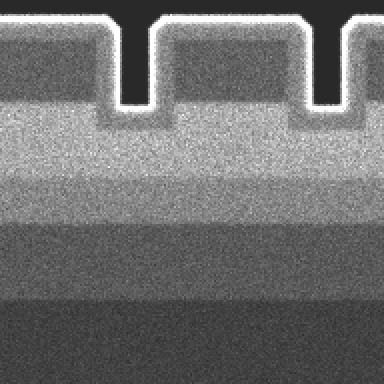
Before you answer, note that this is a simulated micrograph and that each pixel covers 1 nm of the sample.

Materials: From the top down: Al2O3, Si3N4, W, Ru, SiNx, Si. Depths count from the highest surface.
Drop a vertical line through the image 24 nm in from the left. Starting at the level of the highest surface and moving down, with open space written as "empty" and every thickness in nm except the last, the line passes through Al2O3 24, Si3N4 62, W 76, Ru 46, SiNx 76, Si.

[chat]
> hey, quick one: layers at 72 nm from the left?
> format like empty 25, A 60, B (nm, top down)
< Al2O3 24, Si3N4 62, W 76, Ru 46, SiNx 76, Si